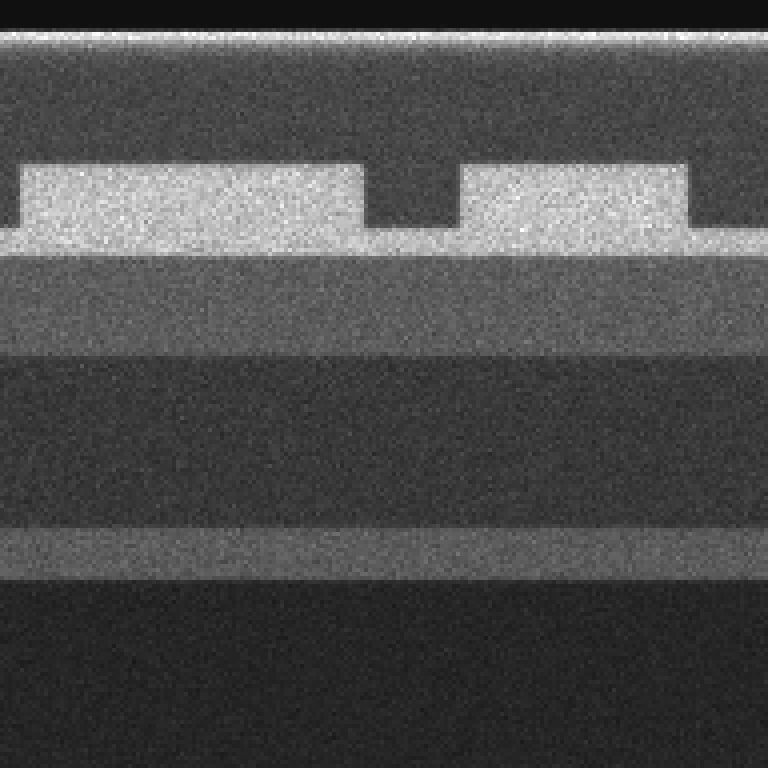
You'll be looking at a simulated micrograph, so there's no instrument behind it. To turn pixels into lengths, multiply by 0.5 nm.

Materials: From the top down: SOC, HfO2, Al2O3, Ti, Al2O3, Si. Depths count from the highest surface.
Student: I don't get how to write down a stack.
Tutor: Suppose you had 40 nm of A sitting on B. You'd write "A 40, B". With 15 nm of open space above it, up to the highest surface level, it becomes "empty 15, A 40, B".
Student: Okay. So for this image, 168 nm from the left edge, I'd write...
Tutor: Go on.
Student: SOC 66, HfO2 46, Al2O3 50, Ti 86, Al2O3 26, Si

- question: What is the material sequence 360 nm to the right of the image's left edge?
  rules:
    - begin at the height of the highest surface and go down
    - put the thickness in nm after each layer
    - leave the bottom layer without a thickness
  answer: SOC 98, HfO2 14, Al2O3 50, Ti 86, Al2O3 26, Si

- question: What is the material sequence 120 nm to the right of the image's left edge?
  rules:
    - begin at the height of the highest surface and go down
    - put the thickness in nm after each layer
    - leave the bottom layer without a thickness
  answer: SOC 66, HfO2 46, Al2O3 50, Ti 86, Al2O3 26, Si